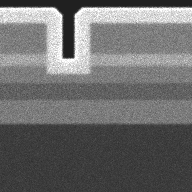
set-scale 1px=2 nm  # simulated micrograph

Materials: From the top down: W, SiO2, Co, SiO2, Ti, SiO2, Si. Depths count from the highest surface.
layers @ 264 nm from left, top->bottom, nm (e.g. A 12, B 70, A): W 30, SiO2 62, Co 24, SiO2 34, Ti 34, SiO2 48, Si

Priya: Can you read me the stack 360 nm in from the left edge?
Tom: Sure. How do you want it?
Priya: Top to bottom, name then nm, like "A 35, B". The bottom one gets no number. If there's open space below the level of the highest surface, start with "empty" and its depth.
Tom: W 30, SiO2 62, Co 24, SiO2 34, Ti 34, SiO2 48, Si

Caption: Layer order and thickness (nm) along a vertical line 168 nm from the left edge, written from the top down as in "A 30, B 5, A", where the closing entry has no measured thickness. W 132, SiO2 18, Ti 34, SiO2 48, Si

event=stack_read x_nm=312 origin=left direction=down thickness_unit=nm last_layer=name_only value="W 30, SiO2 62, Co 24, SiO2 34, Ti 34, SiO2 48, Si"